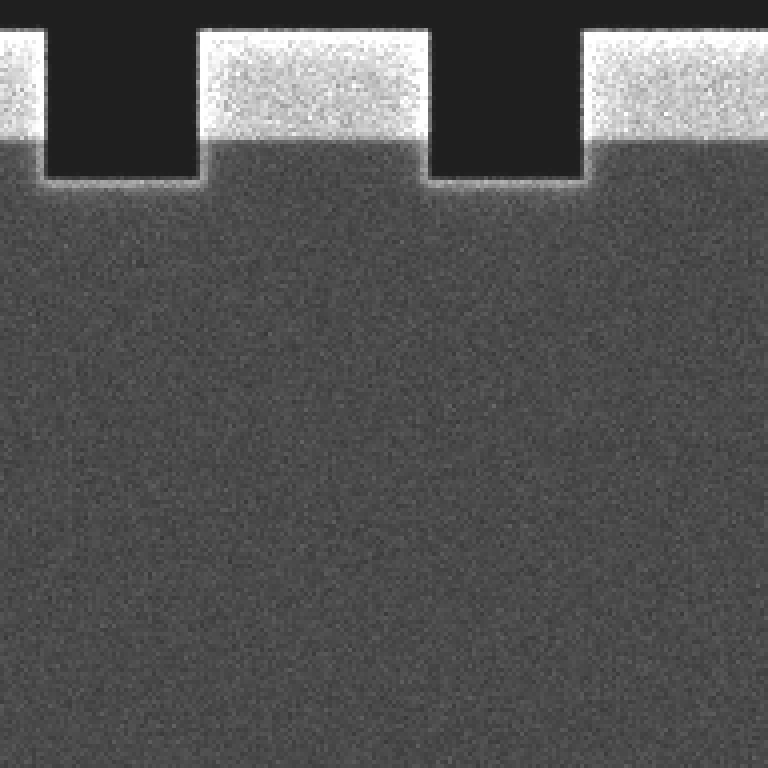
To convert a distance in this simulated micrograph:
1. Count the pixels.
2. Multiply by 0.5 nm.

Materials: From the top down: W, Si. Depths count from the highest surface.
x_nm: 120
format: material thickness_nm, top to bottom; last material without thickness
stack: W 54, Si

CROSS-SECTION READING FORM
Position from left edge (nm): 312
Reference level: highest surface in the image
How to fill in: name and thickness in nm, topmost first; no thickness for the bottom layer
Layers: W 54, Si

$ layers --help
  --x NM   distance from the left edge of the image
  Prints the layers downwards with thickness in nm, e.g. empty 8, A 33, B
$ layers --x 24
empty 74, Si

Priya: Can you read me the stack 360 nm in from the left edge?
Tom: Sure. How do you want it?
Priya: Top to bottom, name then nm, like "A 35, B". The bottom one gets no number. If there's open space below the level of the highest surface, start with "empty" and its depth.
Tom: W 54, Si